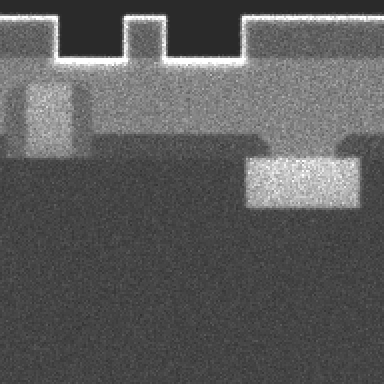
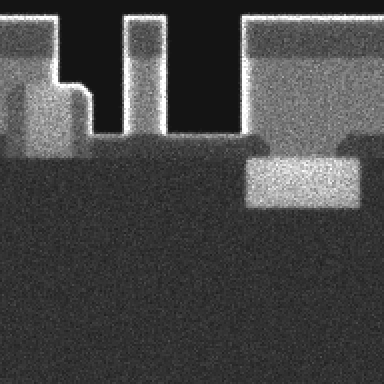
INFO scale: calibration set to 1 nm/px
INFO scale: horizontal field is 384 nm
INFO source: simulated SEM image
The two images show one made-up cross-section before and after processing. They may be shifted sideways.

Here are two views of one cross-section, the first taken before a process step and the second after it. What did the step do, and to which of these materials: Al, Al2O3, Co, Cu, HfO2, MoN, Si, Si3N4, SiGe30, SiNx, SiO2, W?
It removed SiO2.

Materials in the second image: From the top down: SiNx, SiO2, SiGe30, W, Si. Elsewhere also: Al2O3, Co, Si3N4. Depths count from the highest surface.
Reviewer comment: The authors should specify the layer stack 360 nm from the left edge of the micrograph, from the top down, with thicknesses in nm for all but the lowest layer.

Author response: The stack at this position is SiNx 42, SiO2 76, SiGe30 24, Si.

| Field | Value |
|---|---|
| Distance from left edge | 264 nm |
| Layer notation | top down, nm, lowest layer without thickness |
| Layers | SiNx 42, SiO2 84, SiGe30 16, W 50, Si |